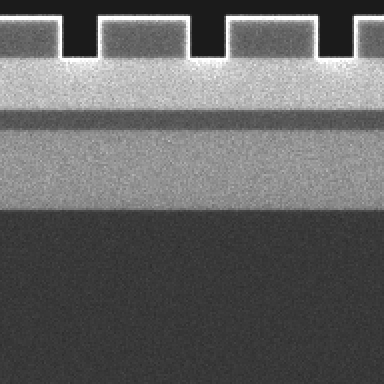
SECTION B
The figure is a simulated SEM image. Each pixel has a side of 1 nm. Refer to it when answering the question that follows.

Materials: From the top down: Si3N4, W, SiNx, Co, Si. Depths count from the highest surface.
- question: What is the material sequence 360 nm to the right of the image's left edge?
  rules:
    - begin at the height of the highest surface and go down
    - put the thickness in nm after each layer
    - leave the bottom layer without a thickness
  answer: Si3N4 42, W 52, SiNx 20, Co 80, Si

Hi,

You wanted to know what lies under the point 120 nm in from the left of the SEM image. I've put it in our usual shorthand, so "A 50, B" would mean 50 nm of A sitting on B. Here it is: Si3N4 42, W 52, SiNx 20, Co 80, Si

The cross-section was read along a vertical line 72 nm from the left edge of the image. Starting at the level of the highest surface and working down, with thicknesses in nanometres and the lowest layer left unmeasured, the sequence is empty 42, W 52, SiNx 20, Co 80, Si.